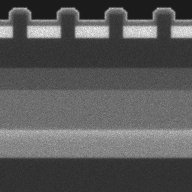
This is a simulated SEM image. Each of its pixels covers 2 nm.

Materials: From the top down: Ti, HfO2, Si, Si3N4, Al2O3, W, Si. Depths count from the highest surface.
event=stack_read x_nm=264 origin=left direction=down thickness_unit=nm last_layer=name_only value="empty 24, Ti 12, HfO2 24, Si 60, Si3N4 44, Al2O3 80, W 56, Si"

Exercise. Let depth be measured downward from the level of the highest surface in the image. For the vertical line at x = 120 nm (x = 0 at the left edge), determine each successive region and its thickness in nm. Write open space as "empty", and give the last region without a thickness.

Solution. empty 4, Ti 32, HfO2 24, Si 60, Si3N4 44, Al2O3 80, W 56, Si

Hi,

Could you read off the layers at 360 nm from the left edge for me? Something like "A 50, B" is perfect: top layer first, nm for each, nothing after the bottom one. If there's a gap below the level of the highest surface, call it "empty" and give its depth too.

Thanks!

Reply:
empty 24, Ti 12, HfO2 24, Si 60, Si3N4 44, Al2O3 80, W 56, Si